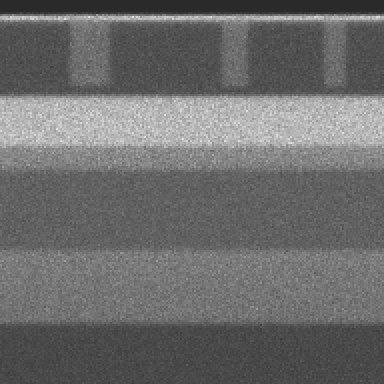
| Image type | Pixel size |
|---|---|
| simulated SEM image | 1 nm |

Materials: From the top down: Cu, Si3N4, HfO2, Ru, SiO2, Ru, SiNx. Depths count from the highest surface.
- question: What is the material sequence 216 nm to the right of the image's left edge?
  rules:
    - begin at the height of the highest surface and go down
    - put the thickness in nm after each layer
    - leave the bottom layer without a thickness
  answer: Si3N4 80, HfO2 50, Ru 24, SiO2 80, Ru 74, SiNx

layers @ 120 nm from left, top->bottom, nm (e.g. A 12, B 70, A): Si3N4 80, HfO2 50, Ru 24, SiO2 80, Ru 74, SiNx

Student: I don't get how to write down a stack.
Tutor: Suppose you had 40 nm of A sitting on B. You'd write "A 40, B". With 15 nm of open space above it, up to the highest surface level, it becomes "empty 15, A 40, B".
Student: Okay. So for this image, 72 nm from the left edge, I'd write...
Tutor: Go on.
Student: Cu 70, Si3N4 10, HfO2 50, Ru 24, SiO2 80, Ru 74, SiNx